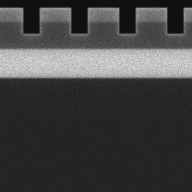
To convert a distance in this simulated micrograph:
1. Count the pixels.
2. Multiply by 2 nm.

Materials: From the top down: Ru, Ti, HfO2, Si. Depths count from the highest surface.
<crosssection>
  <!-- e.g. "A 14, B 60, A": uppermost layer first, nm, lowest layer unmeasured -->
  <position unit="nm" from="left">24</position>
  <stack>Ru 28, Ti 54, HfO2 58, Si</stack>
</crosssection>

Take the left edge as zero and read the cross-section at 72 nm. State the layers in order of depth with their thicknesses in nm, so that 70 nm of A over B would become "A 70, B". empty 52, Ti 30, HfO2 58, Si